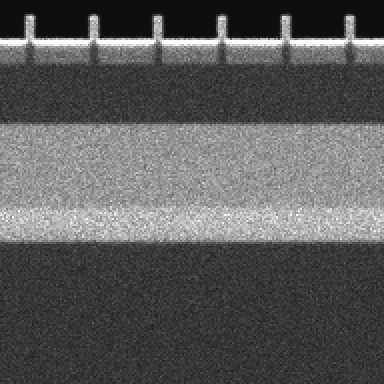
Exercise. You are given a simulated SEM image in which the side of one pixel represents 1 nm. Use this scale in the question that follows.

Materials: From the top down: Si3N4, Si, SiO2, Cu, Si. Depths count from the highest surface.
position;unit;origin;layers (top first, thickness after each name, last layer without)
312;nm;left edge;empty 24, Si3N4 24, Si 60, SiO2 84, Cu 34, Si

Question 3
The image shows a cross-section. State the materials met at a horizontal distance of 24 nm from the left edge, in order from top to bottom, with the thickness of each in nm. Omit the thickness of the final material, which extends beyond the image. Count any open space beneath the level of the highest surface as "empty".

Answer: empty 24, Si3N4 24, Si 60, SiO2 84, Cu 34, Si